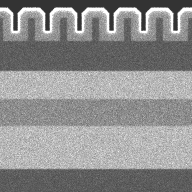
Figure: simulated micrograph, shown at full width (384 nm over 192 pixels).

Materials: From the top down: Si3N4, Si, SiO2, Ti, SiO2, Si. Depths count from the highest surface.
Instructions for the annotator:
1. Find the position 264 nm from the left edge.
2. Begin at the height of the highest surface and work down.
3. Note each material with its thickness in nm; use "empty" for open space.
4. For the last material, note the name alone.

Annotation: Si3N4 66, Si 60, SiO2 56, Ti 54, SiO2 86, Si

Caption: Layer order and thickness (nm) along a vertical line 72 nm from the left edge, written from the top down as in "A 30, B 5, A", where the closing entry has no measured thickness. Si3N4 66, Si 60, SiO2 56, Ti 54, SiO2 86, Si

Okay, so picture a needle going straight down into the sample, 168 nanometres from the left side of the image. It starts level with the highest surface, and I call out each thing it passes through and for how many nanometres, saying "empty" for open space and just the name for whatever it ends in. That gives empty 6, Si3N4 60, Si 60, SiO2 56, Ti 54, SiO2 86, Si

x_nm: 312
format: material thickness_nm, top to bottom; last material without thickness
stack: Si3N4 20, Si 106, SiO2 56, Ti 54, SiO2 86, Si